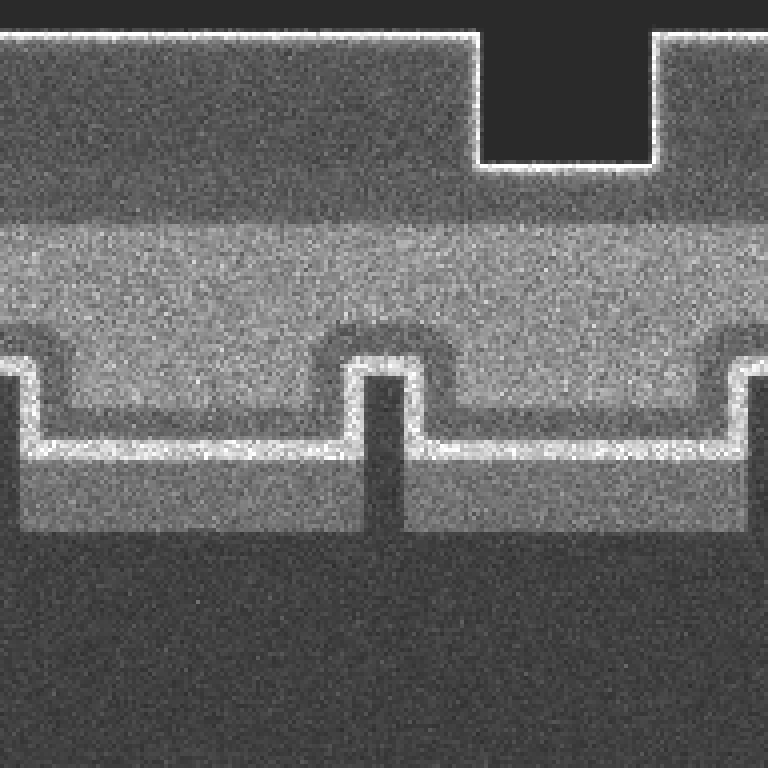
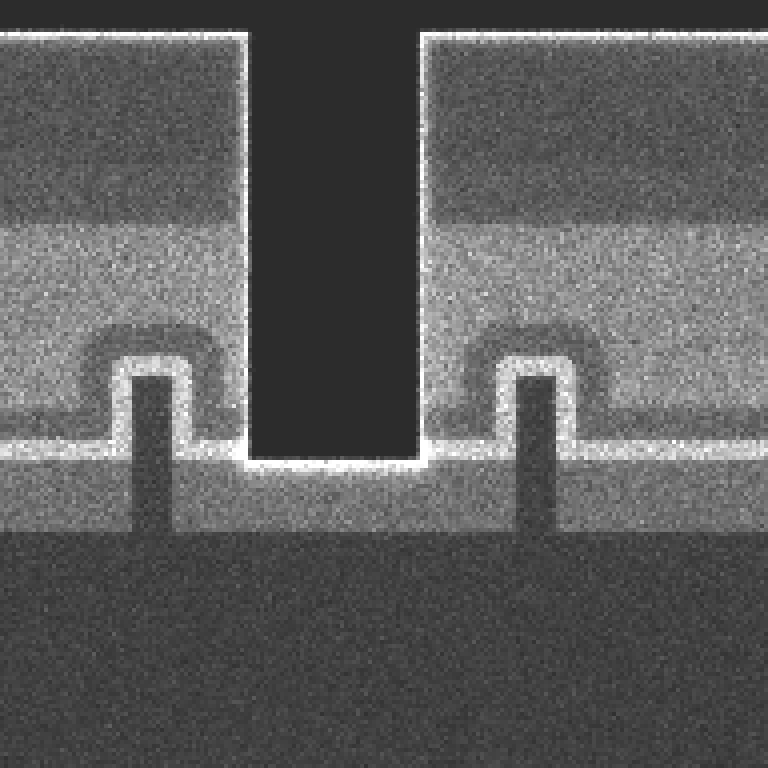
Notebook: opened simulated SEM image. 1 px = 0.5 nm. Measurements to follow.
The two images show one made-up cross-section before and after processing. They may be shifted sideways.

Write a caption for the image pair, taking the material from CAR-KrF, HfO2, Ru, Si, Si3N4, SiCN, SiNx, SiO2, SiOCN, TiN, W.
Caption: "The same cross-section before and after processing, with HfO2 and Ru and Si3N4 and TiN removed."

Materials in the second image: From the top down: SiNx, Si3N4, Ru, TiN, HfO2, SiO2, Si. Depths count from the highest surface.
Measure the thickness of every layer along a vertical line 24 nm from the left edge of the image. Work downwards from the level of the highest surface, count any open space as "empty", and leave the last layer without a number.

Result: SiNx 66, Si3N4 30, Ru 92, TiN 16, HfO2 10, SiO2 36, Si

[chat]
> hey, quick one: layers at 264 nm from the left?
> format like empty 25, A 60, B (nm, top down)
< SiNx 66, Si3N4 30, Ru 50, TiN 16, HfO2 10, Si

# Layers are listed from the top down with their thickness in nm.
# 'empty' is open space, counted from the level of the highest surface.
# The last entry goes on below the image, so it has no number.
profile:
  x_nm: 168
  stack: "empty 214, SiO2 36, Si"